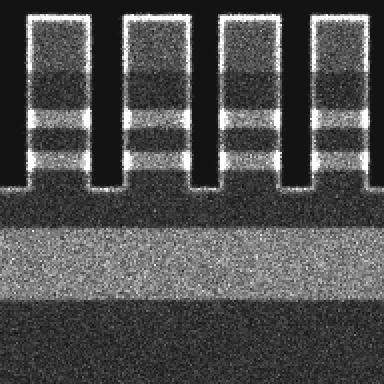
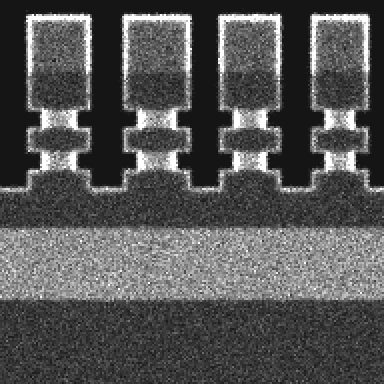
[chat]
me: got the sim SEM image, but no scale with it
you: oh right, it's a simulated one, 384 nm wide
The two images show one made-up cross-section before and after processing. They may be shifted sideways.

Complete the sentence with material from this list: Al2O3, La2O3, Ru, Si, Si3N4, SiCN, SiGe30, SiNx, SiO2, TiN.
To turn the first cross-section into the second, Al2O3 must be removed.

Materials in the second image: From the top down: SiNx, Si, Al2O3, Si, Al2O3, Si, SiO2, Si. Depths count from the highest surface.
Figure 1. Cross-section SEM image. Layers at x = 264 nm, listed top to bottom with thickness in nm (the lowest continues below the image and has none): SiNx 56, Si 38, Al2O3 18, Si 24, Al2O3 18, Si 58, SiO2 72, Si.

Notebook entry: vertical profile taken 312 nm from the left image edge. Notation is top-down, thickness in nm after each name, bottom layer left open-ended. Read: SiNx 56, Si 38, empty 18, Si 24, empty 18, Si 58, SiO2 72, Si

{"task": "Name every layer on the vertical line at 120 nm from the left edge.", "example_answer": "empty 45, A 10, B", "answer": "empty 172, Si 40, SiO2 72, Si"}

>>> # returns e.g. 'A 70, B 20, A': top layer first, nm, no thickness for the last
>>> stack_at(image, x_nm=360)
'SiNx 56, Si 38, empty 18, Si 24, empty 18, Si 58, SiO2 72, Si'